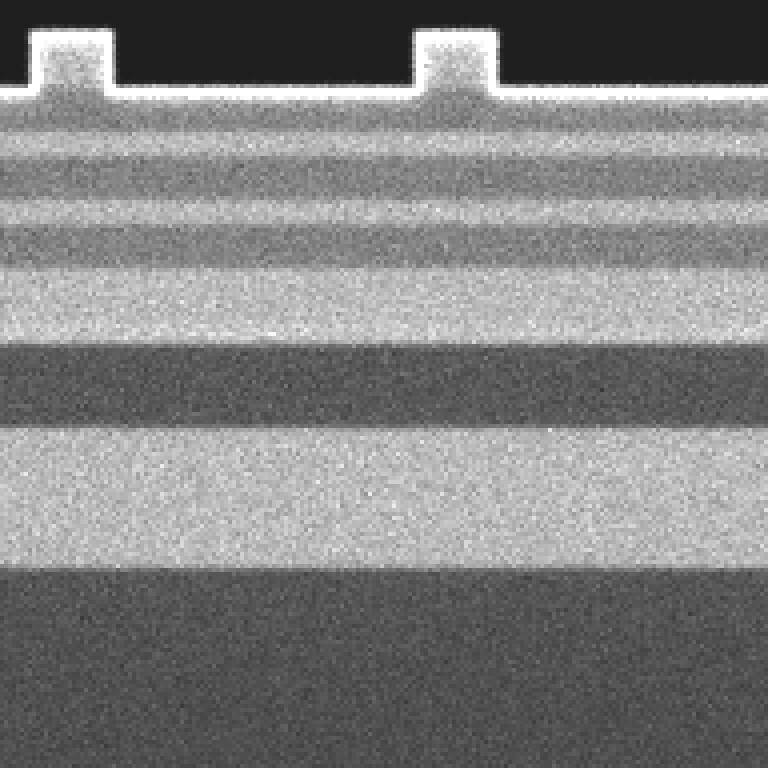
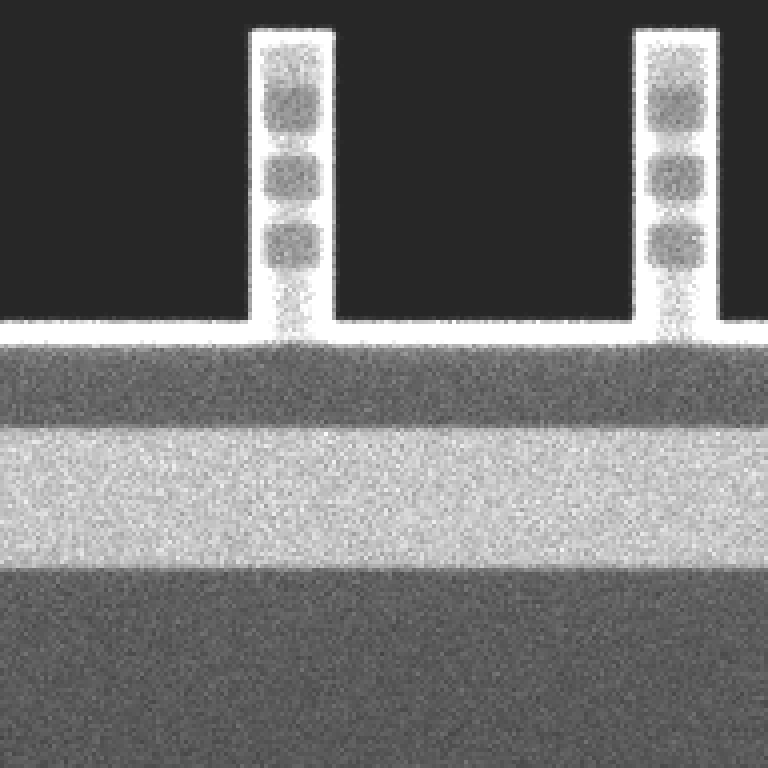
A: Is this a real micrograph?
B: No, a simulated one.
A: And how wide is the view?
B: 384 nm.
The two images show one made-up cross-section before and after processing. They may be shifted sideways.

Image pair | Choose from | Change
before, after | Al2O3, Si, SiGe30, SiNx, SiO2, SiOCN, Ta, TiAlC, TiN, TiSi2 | SiNx and SiO2 (removed)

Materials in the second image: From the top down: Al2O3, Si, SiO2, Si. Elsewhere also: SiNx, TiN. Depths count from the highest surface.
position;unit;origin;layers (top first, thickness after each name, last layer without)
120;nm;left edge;empty 146, Al2O3 10, Si 42, SiO2 70, Si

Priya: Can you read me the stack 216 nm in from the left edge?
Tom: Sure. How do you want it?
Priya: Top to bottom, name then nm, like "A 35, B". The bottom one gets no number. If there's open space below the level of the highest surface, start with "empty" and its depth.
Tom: empty 146, Al2O3 10, Si 42, SiO2 70, Si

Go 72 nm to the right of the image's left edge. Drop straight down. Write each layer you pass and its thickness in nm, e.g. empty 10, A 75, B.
empty 146, Al2O3 10, Si 42, SiO2 70, Si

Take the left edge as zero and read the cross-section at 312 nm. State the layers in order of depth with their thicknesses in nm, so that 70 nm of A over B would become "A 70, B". empty 146, Al2O3 10, Si 42, SiO2 70, Si